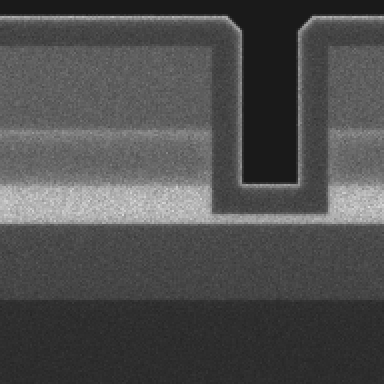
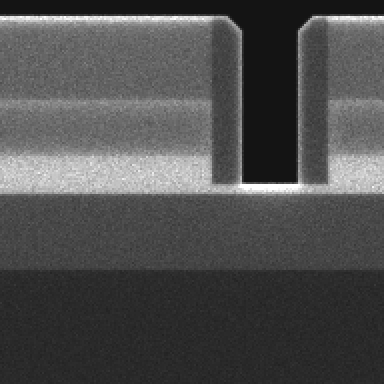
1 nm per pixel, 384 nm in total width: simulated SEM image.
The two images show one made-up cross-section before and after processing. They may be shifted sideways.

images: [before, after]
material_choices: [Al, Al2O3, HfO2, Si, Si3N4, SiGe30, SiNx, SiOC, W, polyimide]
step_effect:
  removed: SiNx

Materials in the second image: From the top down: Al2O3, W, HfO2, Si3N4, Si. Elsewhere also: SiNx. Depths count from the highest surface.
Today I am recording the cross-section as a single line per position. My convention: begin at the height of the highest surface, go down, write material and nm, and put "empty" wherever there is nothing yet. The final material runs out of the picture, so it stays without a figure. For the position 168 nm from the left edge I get Al2O3 84, W 56, HfO2 38, Si3N4 76, Si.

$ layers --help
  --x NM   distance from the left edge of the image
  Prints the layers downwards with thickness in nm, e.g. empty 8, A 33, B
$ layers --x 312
SiNx 168, HfO2 10, Si3N4 76, Si